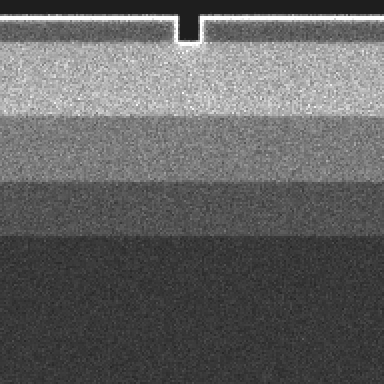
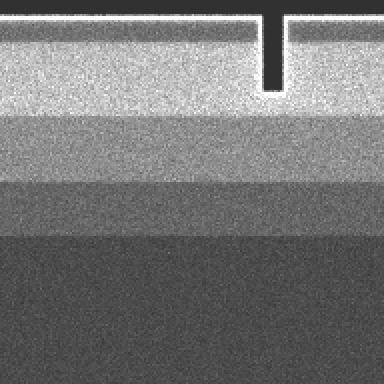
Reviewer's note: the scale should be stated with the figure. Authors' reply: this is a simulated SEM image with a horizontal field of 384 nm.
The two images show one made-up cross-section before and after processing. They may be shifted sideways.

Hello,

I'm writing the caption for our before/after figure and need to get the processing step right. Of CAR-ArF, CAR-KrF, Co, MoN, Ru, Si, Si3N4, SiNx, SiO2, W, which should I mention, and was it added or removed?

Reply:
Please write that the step removed W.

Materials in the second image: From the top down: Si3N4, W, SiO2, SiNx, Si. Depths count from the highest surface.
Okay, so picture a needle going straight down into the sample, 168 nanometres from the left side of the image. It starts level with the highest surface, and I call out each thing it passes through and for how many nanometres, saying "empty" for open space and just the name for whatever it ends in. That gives Si3N4 26, W 74, SiO2 66, SiNx 54, Si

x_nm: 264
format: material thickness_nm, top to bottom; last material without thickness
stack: empty 76, W 24, SiO2 66, SiNx 54, Si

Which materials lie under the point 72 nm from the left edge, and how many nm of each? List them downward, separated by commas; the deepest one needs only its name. Si3N4 26, W 74, SiO2 66, SiNx 54, Si